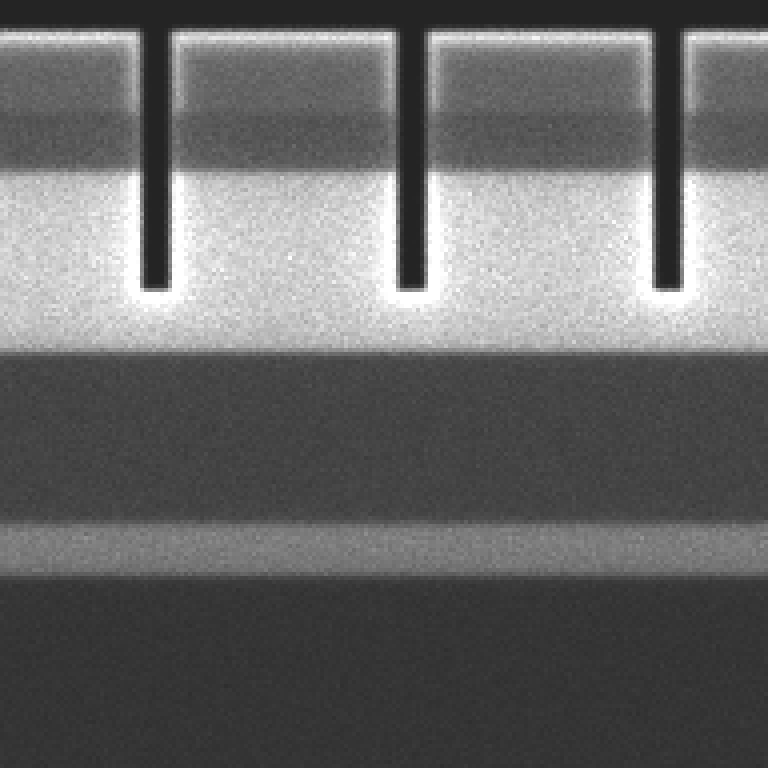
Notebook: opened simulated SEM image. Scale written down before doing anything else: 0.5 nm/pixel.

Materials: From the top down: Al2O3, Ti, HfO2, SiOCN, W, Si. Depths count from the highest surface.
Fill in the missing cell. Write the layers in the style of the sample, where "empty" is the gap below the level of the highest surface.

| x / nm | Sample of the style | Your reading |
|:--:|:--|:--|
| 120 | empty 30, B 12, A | Al2O3 40, Ti 30, HfO2 90, SiOCN 86, W 26, Si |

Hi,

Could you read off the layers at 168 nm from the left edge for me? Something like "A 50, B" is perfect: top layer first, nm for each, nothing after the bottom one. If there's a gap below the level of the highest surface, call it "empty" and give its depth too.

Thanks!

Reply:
Al2O3 40, Ti 30, HfO2 90, SiOCN 86, W 26, Si